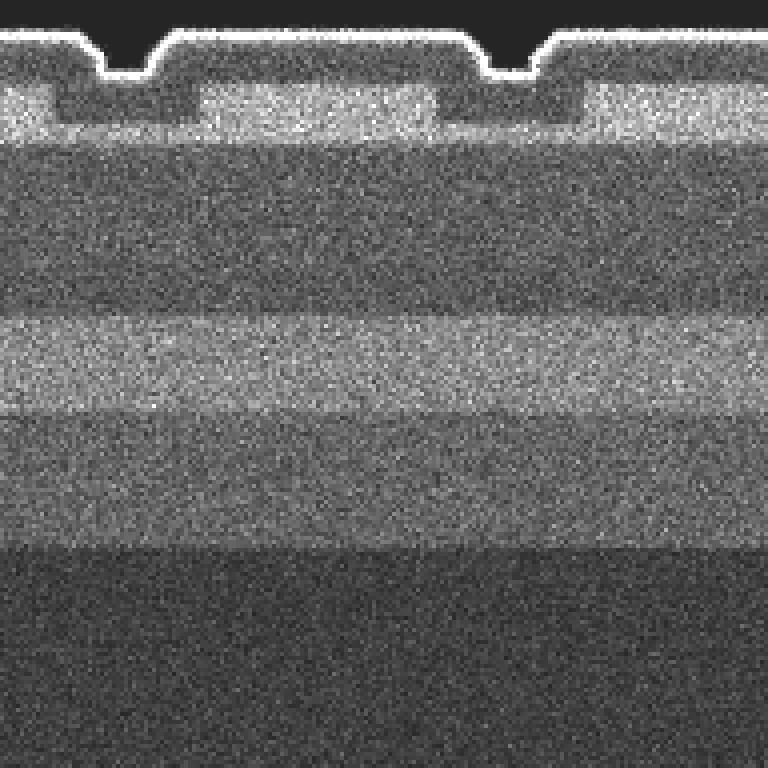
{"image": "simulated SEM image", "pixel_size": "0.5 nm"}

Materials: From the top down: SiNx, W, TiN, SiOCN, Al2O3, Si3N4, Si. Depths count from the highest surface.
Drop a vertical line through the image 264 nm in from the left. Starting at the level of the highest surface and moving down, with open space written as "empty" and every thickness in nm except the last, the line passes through empty 20, SiNx 26, W 10, TiN 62, SiOCN 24, Al2O3 48, Si3N4 68, Si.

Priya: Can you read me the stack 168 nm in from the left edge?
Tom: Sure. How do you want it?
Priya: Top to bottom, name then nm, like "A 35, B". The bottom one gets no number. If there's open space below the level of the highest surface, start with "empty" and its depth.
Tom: SiNx 26, W 30, TiN 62, SiOCN 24, Al2O3 48, Si3N4 68, Si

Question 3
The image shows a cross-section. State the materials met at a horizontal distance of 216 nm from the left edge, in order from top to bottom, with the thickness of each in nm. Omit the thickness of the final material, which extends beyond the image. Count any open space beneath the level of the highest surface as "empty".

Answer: SiNx 26, W 30, TiN 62, SiOCN 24, Al2O3 48, Si3N4 68, Si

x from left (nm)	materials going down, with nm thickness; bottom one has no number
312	SiNx 26, W 30, TiN 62, SiOCN 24, Al2O3 48, Si3N4 68, Si